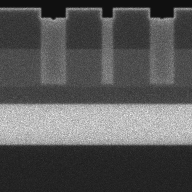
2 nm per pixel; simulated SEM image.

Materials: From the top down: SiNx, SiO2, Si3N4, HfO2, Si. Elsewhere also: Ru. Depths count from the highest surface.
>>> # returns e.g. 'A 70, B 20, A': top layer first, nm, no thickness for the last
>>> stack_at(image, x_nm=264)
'SiNx 82, SiO2 76, Si3N4 34, HfO2 82, Si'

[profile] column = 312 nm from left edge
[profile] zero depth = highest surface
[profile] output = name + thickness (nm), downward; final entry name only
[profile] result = empty 20, Ru 132, SiO2 6, Si3N4 34, HfO2 82, Si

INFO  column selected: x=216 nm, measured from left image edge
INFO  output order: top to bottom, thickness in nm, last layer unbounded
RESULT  empty 20, Ru 132, SiO2 6, Si3N4 34, HfO2 82, Si